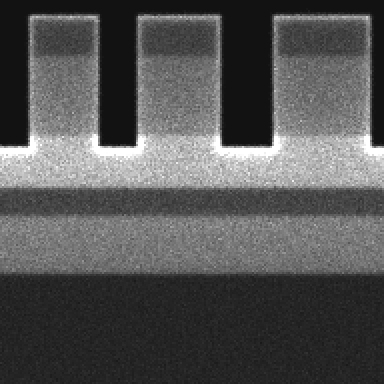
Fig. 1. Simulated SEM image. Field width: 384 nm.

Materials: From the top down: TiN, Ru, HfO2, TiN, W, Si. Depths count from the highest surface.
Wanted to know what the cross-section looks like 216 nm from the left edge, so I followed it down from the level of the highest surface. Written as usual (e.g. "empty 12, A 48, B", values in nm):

TiN 40, Ru 80, HfO2 52, TiN 28, W 58, Si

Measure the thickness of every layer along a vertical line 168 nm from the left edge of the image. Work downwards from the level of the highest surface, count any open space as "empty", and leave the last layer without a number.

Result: TiN 40, Ru 80, HfO2 52, TiN 28, W 58, Si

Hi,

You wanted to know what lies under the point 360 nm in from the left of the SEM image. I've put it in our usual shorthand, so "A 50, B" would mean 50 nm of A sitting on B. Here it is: TiN 40, Ru 80, HfO2 52, TiN 28, W 58, Si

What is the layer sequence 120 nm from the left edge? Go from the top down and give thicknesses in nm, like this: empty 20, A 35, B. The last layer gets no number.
empty 132, HfO2 40, TiN 28, W 58, Si